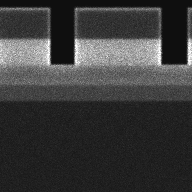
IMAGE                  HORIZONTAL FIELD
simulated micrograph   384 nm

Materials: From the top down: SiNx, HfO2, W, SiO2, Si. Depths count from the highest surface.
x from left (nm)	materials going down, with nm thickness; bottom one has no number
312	SiNx 62, HfO2 52, W 40, SiO2 32, Si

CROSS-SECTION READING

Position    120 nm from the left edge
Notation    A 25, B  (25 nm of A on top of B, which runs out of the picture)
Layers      empty 114, W 40, SiO2 32, Si